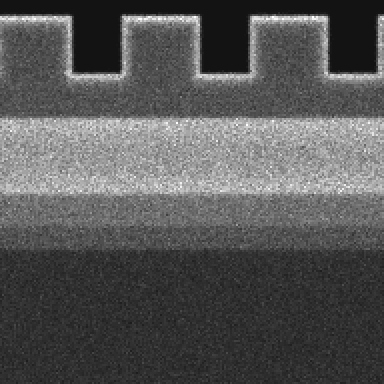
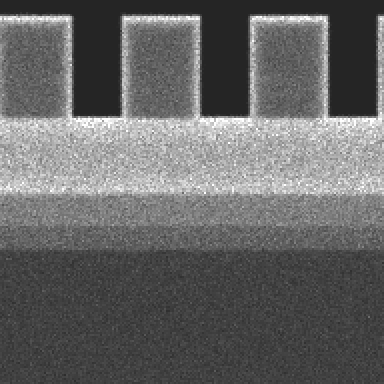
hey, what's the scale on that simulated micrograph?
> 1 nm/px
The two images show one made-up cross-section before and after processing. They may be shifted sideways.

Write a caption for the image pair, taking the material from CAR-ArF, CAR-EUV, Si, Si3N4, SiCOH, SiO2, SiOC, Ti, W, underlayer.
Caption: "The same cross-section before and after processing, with underlayer removed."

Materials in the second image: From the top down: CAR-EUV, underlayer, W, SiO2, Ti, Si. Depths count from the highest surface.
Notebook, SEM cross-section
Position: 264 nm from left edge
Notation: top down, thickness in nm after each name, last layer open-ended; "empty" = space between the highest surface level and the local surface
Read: CAR-EUV 58, underlayer 44, W 76, SiO2 32, Ti 24, Si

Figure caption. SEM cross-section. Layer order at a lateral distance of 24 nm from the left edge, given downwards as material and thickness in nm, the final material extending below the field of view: CAR-EUV 58, underlayer 44, W 76, SiO2 32, Ti 24, Si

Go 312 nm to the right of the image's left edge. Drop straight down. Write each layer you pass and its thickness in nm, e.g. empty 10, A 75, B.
CAR-EUV 58, underlayer 44, W 76, SiO2 32, Ti 24, Si